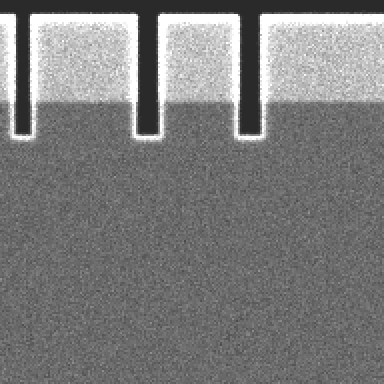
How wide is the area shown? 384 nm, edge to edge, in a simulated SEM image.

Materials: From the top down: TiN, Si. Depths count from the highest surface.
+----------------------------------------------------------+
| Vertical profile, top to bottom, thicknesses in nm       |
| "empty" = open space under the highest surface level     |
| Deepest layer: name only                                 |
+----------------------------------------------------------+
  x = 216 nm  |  TiN 86, Si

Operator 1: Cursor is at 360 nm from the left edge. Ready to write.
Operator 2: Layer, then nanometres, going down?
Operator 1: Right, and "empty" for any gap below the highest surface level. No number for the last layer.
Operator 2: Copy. TiN 86, Si